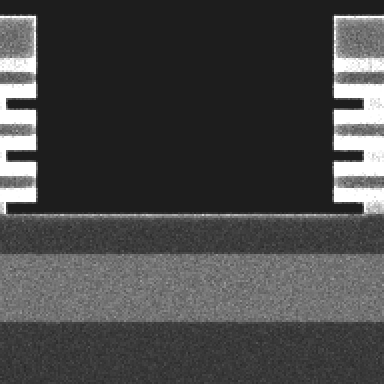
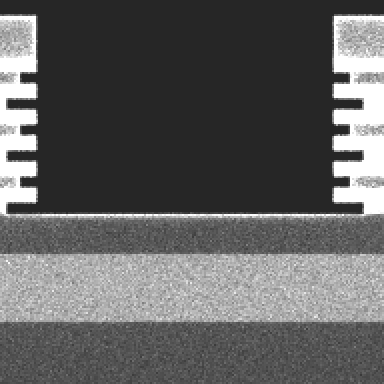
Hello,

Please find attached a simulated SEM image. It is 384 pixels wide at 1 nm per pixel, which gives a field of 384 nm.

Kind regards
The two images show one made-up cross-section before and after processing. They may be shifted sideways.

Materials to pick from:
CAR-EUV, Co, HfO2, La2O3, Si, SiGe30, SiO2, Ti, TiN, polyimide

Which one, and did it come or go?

SiGe30 - removed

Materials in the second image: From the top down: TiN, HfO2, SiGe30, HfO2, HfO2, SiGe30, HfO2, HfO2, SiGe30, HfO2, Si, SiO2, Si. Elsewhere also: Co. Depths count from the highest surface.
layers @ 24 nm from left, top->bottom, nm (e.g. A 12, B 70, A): TiN 42, HfO2 14, empty 12, HfO2 14, empty 12, HfO2 14, empty 12, HfO2 14, empty 12, HfO2 14, empty 12, HfO2 14, empty 12, Si 40, SiO2 68, Si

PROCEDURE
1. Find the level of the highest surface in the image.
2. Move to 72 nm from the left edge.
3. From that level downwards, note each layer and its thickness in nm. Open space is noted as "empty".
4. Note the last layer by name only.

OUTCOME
empty 198, Si 40, SiO2 68, Si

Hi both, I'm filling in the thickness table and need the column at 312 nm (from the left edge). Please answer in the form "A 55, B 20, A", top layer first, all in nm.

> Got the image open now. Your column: empty 198, Si 40, SiO2 68, Si